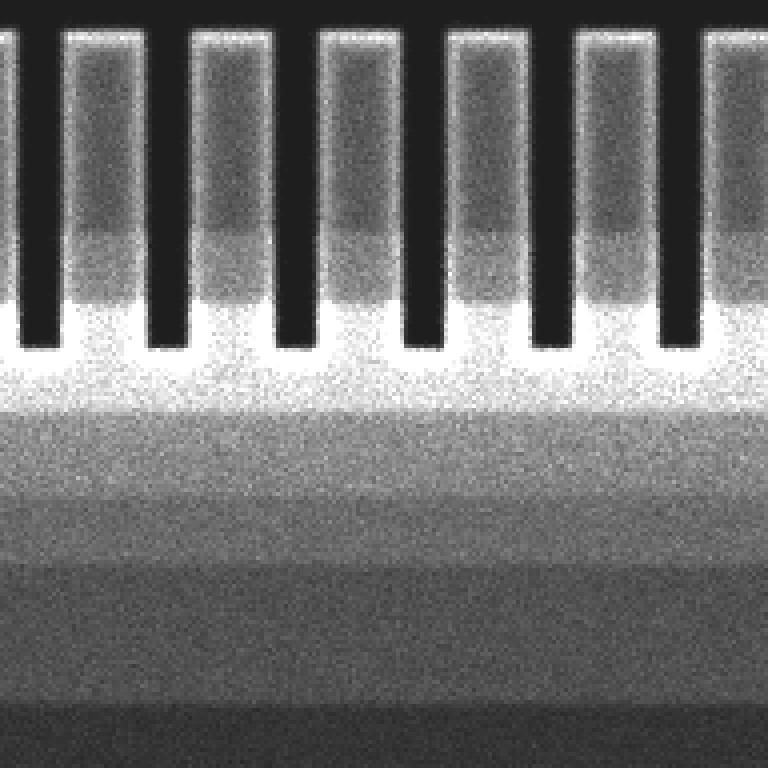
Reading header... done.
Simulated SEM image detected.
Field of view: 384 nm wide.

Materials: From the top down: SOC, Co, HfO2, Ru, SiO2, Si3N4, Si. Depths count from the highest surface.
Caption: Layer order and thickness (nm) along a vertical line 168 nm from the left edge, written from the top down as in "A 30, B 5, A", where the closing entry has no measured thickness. SOC 100, Co 36, HfO2 54, Ru 42, SiO2 34, Si3N4 70, Si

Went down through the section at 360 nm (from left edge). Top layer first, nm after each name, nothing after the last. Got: SOC 100, Co 36, HfO2 54, Ru 42, SiO2 34, Si3N4 70, Si